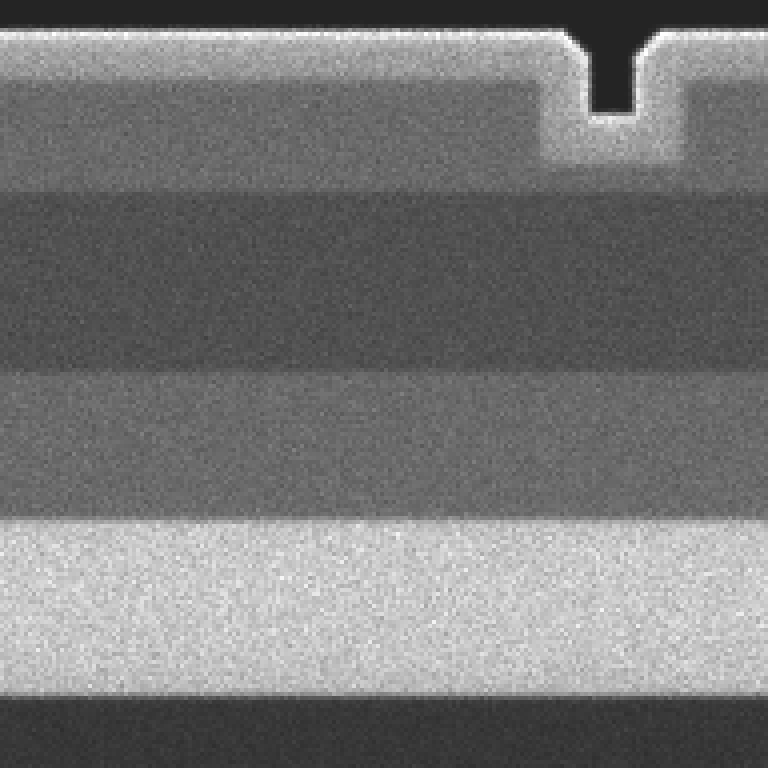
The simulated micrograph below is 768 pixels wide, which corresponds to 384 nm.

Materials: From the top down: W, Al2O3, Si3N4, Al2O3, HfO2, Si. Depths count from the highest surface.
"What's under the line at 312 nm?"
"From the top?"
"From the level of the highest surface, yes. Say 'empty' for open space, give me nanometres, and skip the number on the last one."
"empty 42, W 24, Al2O3 14, Si3N4 90, Al2O3 74, HfO2 88, Si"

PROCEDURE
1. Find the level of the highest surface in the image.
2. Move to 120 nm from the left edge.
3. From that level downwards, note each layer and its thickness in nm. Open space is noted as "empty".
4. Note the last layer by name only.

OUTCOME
W 24, Al2O3 56, Si3N4 90, Al2O3 74, HfO2 88, Si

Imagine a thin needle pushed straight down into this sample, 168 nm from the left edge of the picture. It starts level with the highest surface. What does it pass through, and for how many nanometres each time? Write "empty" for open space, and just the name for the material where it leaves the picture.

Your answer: W 24, Al2O3 56, Si3N4 90, Al2O3 74, HfO2 88, Si